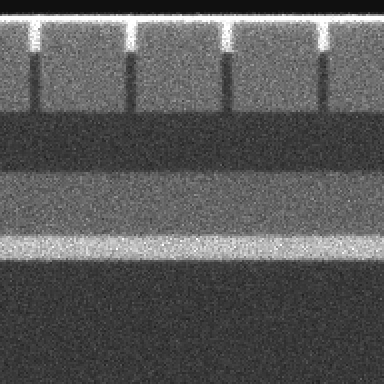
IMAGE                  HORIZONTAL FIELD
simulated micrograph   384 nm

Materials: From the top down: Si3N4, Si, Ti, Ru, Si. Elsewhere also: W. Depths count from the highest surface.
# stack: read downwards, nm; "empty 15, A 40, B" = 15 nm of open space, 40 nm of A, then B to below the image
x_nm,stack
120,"Si3N4 96, Si 60, Ti 64, Ru 24, Si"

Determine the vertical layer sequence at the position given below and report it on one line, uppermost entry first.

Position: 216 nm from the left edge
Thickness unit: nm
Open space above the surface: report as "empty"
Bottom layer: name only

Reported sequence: Si3N4 96, Si 60, Ti 64, Ru 24, Si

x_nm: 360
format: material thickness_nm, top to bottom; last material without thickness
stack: Si3N4 96, Si 60, Ti 64, Ru 24, Si